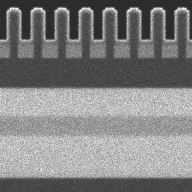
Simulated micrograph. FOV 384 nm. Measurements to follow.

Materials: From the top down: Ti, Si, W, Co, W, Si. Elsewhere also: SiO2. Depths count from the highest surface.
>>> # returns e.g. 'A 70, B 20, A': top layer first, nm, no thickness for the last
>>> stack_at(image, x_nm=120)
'Ti 10, Si 150, W 56, Co 40, W 84, Si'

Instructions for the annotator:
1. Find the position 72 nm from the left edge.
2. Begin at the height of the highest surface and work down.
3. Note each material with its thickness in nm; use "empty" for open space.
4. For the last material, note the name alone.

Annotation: Ti 10, Si 150, W 56, Co 40, W 84, Si